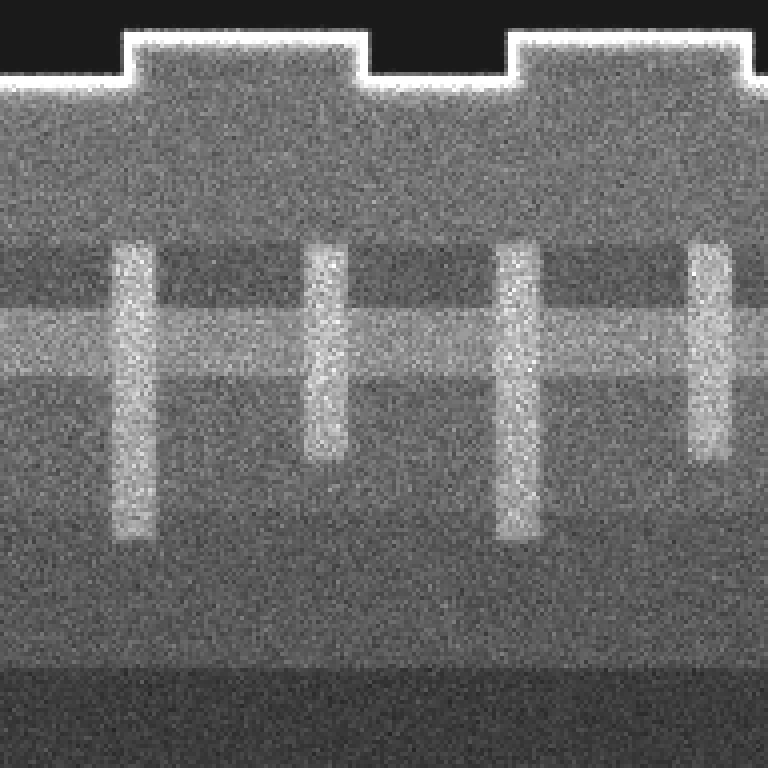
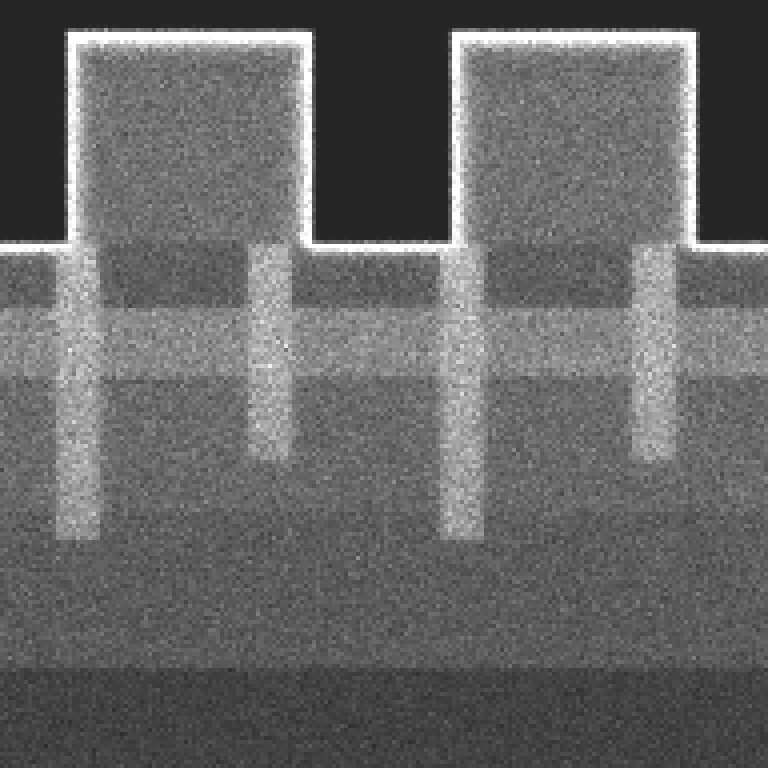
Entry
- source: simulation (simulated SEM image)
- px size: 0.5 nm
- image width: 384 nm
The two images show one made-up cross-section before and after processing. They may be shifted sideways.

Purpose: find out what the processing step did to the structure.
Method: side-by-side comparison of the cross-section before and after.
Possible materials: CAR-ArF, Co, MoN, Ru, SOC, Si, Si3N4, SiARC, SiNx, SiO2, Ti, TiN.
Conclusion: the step removed SOC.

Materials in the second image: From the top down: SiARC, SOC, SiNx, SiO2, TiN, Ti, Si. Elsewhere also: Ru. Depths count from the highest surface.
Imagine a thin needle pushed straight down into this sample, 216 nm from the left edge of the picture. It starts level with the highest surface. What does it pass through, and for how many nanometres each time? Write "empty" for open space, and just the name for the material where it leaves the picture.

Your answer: empty 106, SiNx 32, SiO2 34, TiN 68, Ti 78, Si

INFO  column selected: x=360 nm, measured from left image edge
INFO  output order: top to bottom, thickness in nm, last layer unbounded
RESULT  empty 106, SiNx 32, SiO2 34, TiN 68, Ti 78, Si